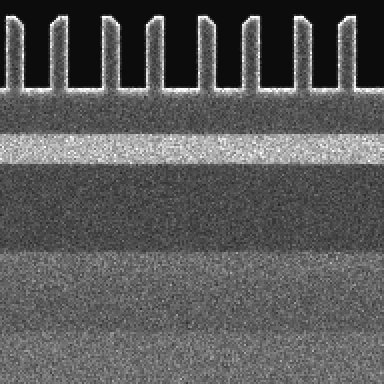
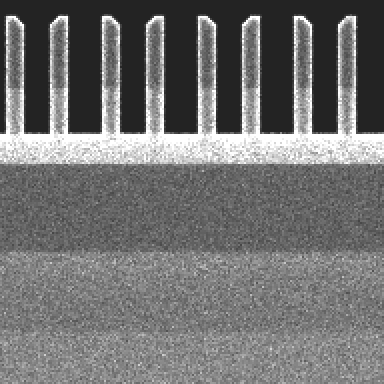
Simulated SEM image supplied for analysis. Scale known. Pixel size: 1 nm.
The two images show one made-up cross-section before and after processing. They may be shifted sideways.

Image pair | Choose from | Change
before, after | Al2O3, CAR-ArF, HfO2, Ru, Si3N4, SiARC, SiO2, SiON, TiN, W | Al2O3 (removed)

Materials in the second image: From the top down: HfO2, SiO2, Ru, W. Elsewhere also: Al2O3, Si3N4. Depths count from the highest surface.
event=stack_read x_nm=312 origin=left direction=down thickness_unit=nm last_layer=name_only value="empty 118, HfO2 30, SiO2 88, Ru 80, W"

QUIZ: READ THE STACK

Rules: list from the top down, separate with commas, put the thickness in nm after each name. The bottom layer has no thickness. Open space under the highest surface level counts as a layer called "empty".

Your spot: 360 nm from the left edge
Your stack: empty 118, HfO2 30, SiO2 88, Ru 80, W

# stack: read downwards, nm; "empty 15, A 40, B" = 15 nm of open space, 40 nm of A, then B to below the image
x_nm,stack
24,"empty 118, HfO2 30, SiO2 88, Ru 80, W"